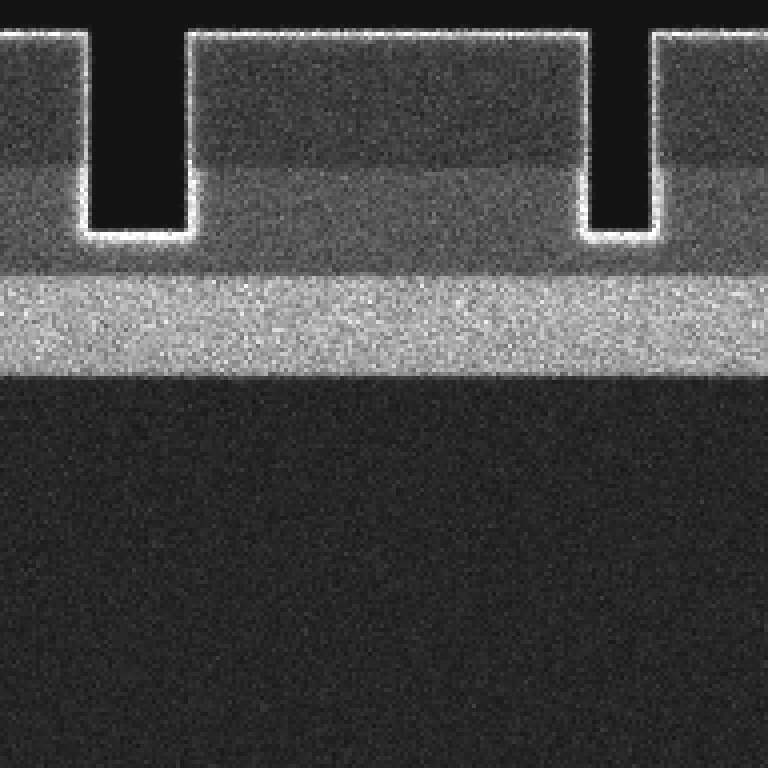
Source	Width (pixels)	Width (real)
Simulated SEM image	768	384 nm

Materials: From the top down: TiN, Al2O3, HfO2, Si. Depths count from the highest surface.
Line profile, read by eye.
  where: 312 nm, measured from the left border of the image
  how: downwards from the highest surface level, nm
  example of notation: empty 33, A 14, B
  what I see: empty 100, Al2O3 22, HfO2 50, Si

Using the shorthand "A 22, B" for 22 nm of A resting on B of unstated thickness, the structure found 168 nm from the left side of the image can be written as TiN 68, Al2O3 54, HfO2 50, Si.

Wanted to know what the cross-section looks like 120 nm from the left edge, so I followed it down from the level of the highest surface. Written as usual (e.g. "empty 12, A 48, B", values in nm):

TiN 68, Al2O3 54, HfO2 50, Si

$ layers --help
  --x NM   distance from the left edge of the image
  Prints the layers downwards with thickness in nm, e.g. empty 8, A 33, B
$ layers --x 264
TiN 68, Al2O3 54, HfO2 50, Si